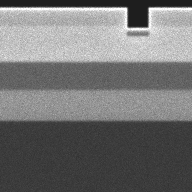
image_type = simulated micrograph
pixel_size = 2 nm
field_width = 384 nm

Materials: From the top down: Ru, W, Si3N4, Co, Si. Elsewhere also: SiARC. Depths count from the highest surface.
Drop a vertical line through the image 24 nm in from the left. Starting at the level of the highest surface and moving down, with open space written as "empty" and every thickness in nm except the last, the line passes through Ru 36, W 72, Si3N4 56, Co 62, Si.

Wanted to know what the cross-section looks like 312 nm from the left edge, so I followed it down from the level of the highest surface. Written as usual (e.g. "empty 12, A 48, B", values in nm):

Ru 36, W 72, Si3N4 56, Co 62, Si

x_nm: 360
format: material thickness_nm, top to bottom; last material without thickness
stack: Ru 36, W 72, Si3N4 56, Co 62, Si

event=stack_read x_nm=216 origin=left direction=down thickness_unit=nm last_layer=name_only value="Ru 36, W 72, Si3N4 56, Co 62, Si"